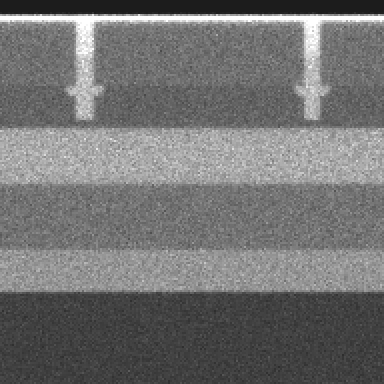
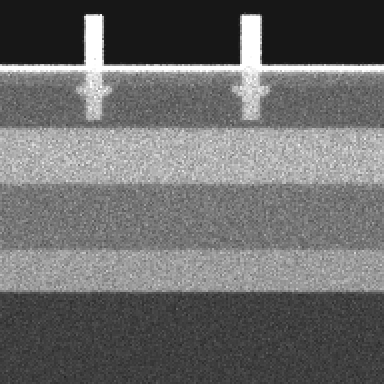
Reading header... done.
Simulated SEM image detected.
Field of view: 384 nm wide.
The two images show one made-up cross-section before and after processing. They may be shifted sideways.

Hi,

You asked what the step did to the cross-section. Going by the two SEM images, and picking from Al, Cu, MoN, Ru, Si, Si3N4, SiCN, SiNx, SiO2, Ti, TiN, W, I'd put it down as Si3N4, removed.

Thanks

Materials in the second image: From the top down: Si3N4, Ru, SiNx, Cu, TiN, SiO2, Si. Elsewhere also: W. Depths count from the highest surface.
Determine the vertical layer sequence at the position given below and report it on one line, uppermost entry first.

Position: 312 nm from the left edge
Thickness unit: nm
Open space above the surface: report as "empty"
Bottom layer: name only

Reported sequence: empty 50, Si3N4 20, SiNx 42, Cu 56, TiN 66, SiO2 42, Si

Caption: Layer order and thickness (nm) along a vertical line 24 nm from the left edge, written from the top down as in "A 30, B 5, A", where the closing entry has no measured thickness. empty 50, Si3N4 20, SiNx 42, Cu 56, TiN 66, SiO2 42, Si